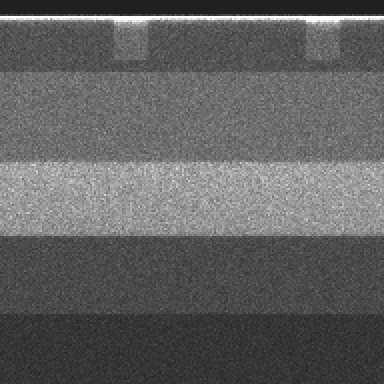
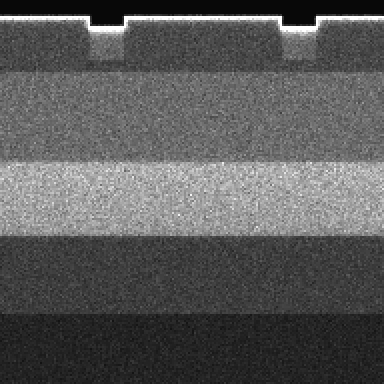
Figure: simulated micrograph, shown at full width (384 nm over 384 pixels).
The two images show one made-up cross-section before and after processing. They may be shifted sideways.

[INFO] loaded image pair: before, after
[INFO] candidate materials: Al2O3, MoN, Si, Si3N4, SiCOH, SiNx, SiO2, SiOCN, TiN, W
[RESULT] removed SiO2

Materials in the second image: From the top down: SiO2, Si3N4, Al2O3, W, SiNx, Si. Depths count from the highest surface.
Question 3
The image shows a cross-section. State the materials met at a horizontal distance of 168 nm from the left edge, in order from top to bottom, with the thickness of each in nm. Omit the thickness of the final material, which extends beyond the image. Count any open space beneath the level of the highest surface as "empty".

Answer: Si3N4 56, Al2O3 90, W 74, SiNx 78, Si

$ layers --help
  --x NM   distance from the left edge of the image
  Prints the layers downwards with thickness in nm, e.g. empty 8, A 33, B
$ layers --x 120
empty 10, SiO2 34, Si3N4 12, Al2O3 90, W 74, SiNx 78, Si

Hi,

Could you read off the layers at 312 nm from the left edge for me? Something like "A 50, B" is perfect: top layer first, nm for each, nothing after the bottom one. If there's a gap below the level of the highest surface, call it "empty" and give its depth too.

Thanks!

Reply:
empty 10, SiO2 34, Si3N4 12, Al2O3 90, W 74, SiNx 78, Si